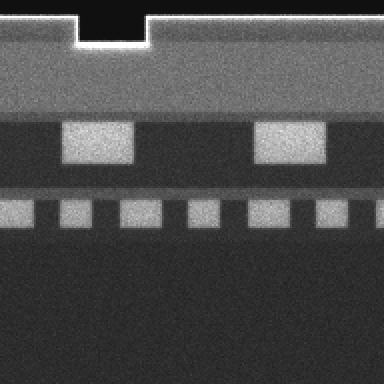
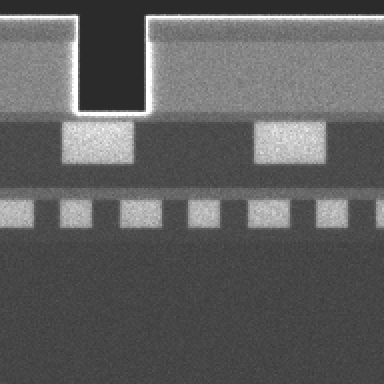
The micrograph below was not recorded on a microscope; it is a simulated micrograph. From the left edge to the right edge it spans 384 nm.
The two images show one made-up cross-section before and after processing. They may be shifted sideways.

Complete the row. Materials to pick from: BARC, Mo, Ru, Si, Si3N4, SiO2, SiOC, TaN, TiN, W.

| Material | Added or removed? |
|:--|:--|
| SiO2 | removed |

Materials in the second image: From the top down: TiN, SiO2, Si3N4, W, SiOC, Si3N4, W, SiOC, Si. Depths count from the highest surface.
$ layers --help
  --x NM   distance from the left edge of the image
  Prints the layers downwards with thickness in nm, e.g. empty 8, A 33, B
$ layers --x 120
empty 96, Si3N4 10, W 42, SiOC 24, Si3N4 12, W 28, SiOC 14, Si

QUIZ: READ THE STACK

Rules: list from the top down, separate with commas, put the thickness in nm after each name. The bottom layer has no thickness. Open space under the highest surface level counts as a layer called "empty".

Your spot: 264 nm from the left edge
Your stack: TiN 26, SiO2 70, Si3N4 10, W 42, SiOC 24, Si3N4 12, W 28, SiOC 14, Si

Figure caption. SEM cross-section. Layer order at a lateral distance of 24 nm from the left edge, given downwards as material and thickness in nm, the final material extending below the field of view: TiN 26, SiO2 70, Si3N4 10, SiOC 66, Si3N4 12, W 28, SiOC 14, Si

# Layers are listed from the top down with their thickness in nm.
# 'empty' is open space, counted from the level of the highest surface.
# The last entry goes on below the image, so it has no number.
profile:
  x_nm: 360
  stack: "TiN 26, SiO2 70, Si3N4 10, SiOC 66, Si3N4 12, SiOC 42, Si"